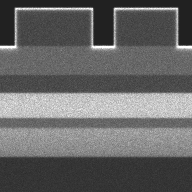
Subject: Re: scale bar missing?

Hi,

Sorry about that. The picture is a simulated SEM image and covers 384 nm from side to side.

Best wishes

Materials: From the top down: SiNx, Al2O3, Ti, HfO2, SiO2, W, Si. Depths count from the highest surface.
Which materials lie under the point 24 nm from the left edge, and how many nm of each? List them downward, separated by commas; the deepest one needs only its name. empty 76, Al2O3 58, Ti 36, HfO2 50, SiO2 20, W 58, Si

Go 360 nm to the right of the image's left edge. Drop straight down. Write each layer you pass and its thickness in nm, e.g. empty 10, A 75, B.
empty 76, Al2O3 58, Ti 36, HfO2 50, SiO2 20, W 58, Si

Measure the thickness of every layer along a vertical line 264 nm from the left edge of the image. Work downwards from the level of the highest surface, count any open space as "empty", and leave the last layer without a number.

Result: SiNx 76, Al2O3 58, Ti 36, HfO2 50, SiO2 20, W 58, Si